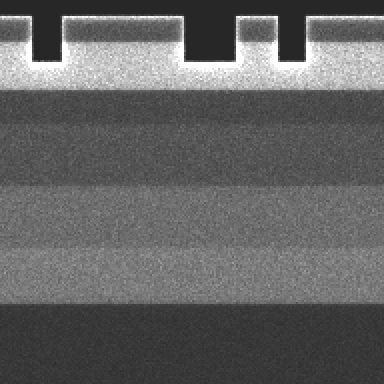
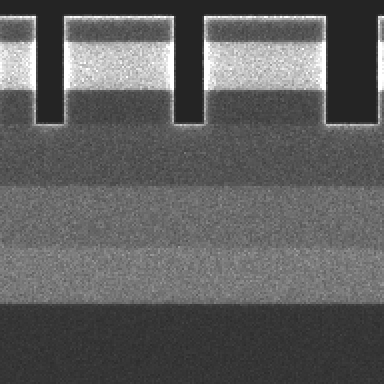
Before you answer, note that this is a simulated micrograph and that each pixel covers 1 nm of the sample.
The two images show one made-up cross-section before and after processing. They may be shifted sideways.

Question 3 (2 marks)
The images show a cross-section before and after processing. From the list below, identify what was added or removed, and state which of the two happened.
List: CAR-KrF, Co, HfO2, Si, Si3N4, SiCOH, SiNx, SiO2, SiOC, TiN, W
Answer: HfO2 and SiNx was removed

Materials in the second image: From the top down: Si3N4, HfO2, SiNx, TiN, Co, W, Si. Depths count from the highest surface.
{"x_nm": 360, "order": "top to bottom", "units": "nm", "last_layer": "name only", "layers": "empty 108, TiN 62, Co 62, W 56, Si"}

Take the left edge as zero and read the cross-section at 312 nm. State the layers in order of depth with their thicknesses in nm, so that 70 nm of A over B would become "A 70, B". Si3N4 26, HfO2 48, SiNx 34, TiN 62, Co 62, W 56, Si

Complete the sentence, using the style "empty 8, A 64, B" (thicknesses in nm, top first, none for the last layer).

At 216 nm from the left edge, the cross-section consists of Si3N4 26, HfO2 48, SiNx 34, TiN 62, Co 62, W 56, Si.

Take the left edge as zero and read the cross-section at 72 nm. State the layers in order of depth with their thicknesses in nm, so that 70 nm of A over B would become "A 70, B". Si3N4 26, HfO2 48, SiNx 34, TiN 62, Co 62, W 56, Si